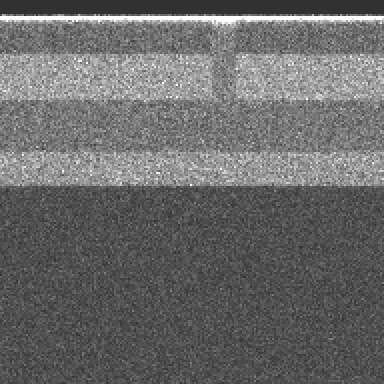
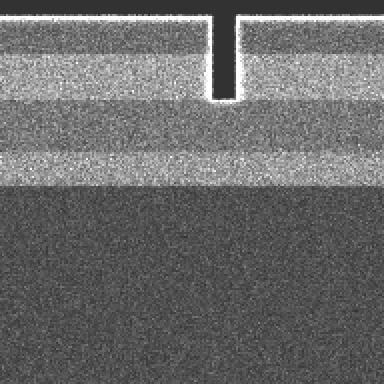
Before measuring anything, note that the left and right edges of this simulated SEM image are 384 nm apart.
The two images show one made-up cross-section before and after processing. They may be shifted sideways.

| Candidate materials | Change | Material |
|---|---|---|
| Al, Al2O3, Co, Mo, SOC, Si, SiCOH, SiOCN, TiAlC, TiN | removed | SOC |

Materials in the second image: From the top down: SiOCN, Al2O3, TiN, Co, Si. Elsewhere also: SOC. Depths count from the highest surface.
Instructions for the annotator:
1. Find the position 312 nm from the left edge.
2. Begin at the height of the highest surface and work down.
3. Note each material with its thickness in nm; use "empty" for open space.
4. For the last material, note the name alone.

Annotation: SiOCN 38, Al2O3 46, TiN 52, Co 34, Si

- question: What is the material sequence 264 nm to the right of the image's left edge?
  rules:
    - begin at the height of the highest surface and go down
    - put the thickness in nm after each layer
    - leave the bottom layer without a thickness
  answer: SiOCN 38, Al2O3 46, TiN 52, Co 34, Si